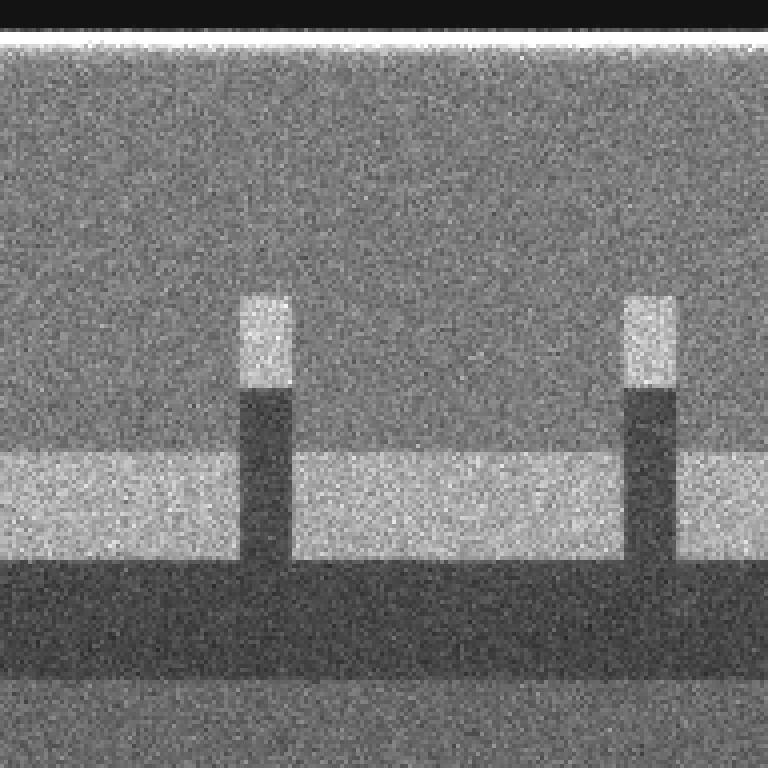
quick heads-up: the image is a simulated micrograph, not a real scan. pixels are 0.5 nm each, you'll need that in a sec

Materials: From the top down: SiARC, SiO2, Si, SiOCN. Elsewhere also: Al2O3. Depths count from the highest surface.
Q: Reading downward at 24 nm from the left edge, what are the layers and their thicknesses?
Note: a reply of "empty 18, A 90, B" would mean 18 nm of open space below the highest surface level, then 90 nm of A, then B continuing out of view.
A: SiARC 210, SiO2 54, Si 60, SiOCN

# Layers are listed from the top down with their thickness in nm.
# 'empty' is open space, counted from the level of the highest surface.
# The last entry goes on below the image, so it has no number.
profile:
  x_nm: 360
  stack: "SiARC 210, SiO2 54, Si 60, SiOCN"